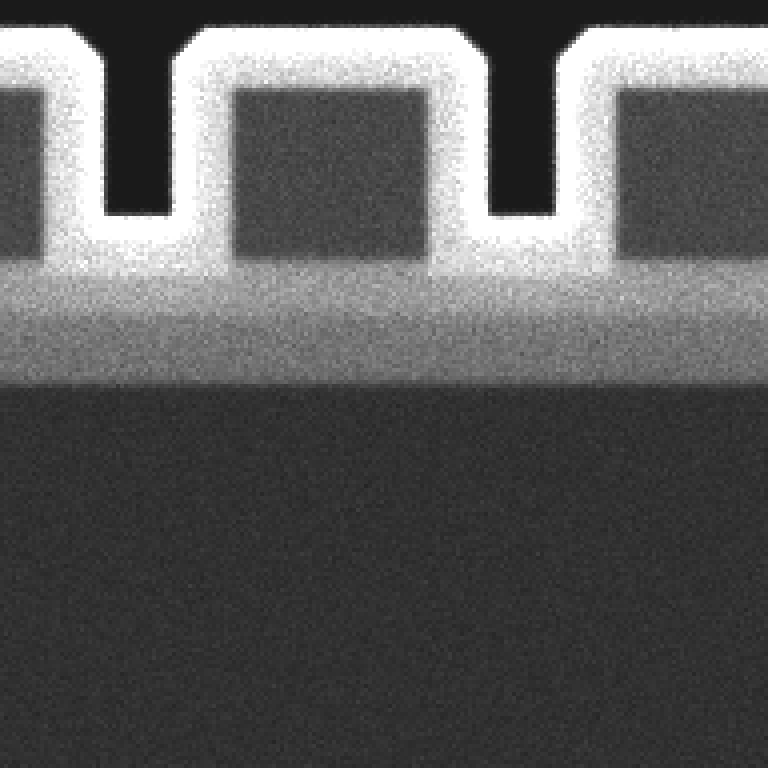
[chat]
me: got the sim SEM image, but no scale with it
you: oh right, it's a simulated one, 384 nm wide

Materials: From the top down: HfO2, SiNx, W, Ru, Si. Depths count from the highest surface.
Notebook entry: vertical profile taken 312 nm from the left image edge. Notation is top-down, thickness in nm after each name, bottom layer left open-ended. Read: HfO2 28, SiNx 86, W 28, Ru 34, Si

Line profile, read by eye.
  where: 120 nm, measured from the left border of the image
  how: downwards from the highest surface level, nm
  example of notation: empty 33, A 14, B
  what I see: HfO2 28, SiNx 86, W 28, Ru 34, Si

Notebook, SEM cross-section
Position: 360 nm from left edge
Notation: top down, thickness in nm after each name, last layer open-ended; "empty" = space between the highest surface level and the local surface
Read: HfO2 28, SiNx 86, W 28, Ru 34, Si